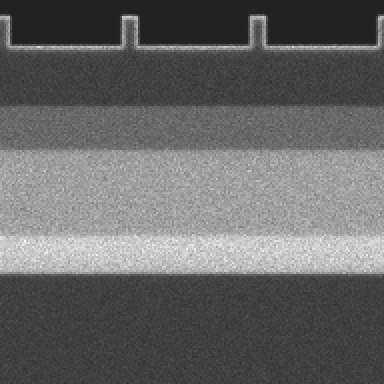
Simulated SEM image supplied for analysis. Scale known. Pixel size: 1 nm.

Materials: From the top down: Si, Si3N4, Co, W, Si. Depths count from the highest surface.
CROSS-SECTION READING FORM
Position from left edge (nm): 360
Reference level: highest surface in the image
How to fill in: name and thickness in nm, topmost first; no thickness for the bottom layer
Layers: empty 30, Si 60, Si3N4 44, Co 86, W 38, Si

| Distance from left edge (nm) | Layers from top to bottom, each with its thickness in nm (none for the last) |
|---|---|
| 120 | empty 30, Si 60, Si3N4 44, Co 86, W 38, Si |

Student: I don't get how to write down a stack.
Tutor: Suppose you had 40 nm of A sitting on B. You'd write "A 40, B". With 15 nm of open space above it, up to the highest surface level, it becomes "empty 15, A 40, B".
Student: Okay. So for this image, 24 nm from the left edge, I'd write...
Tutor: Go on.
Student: empty 30, Si 60, Si3N4 44, Co 86, W 38, Si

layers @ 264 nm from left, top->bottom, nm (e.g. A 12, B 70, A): Si 90, Si3N4 44, Co 86, W 38, Si